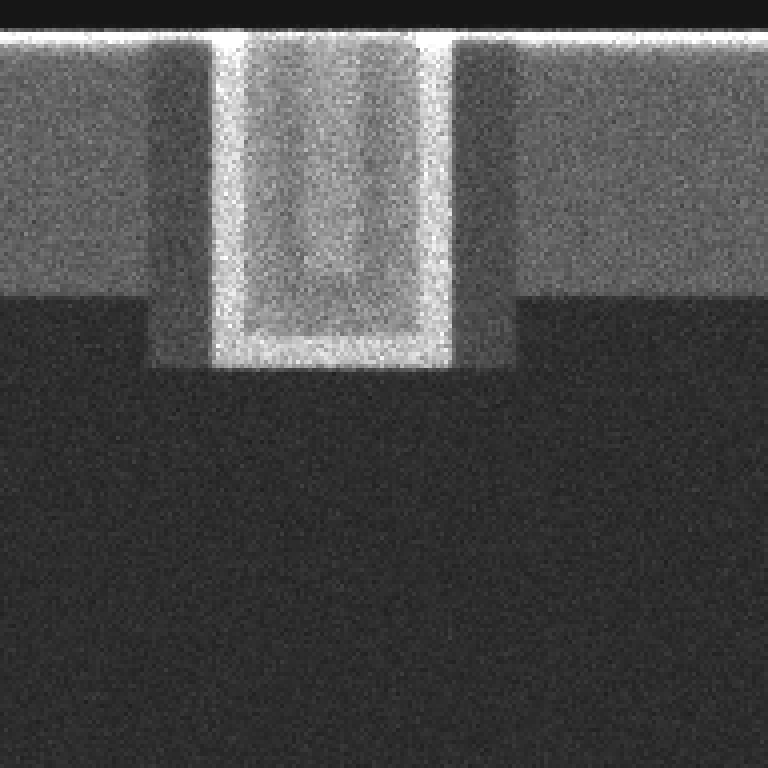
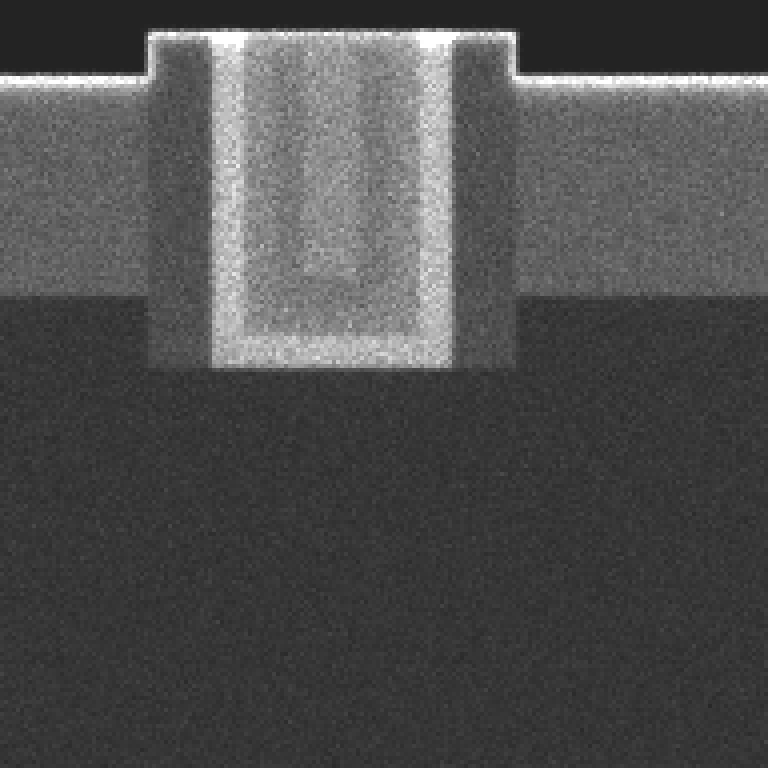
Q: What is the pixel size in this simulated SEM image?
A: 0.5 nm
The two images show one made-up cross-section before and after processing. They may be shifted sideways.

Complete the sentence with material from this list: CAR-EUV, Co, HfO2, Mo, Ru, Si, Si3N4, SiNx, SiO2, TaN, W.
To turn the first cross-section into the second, SiO2 must be removed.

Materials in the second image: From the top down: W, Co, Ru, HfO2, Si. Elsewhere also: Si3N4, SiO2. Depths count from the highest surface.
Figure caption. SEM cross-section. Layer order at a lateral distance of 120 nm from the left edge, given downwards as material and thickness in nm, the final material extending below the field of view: HfO2 168, Si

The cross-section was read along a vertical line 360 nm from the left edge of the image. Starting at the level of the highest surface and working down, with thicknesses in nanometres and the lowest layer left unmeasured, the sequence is empty 22, SiO2 110, Si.